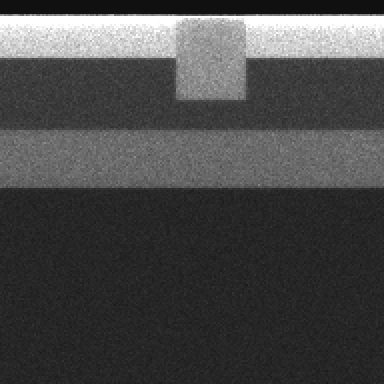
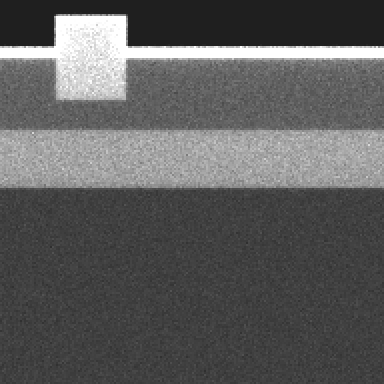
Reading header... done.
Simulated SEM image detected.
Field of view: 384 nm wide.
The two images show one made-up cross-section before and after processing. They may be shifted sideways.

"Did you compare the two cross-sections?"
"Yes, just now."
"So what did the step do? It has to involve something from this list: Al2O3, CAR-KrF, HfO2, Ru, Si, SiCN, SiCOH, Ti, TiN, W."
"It removed HfO2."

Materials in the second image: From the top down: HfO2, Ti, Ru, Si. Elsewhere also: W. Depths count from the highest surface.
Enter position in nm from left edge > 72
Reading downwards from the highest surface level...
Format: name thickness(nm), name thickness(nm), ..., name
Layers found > W 84, Ti 30, Ru 58, Si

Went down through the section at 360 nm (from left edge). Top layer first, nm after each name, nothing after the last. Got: empty 32, HfO2 10, Ti 72, Ru 58, Si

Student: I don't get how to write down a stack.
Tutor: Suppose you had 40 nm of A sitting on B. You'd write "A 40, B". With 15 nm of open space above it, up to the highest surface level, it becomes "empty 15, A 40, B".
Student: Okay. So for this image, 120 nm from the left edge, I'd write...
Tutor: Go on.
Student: W 84, Ti 30, Ru 58, Si